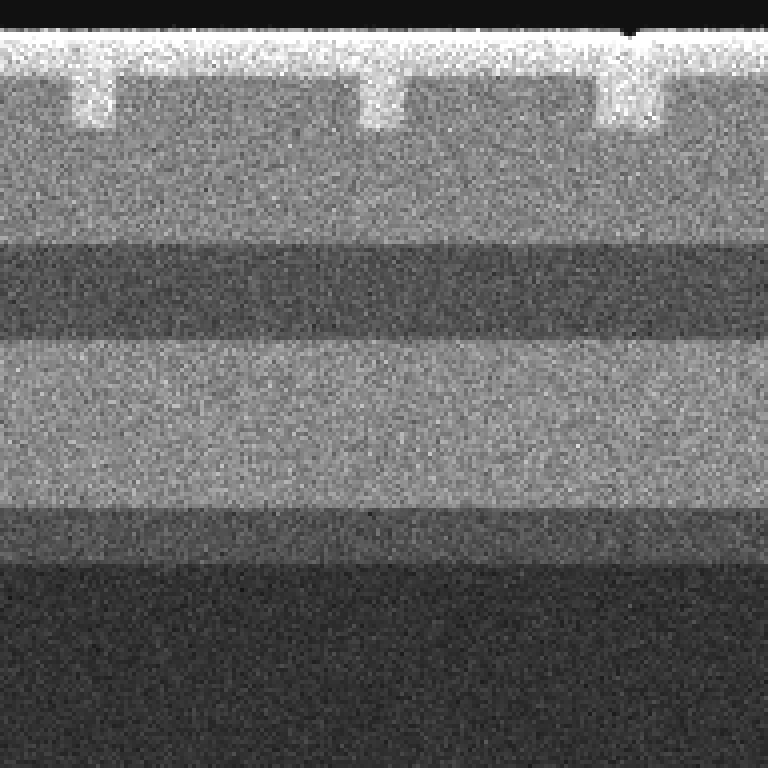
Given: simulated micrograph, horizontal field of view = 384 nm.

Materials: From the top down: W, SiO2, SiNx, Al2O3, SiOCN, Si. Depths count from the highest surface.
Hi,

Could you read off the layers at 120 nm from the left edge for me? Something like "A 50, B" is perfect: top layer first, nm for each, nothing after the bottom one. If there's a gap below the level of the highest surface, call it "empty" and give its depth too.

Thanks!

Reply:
W 22, SiO2 84, SiNx 48, Al2O3 84, SiOCN 28, Si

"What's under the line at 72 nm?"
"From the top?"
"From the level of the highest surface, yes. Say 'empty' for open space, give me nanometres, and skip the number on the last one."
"W 22, SiO2 84, SiNx 48, Al2O3 84, SiOCN 28, Si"